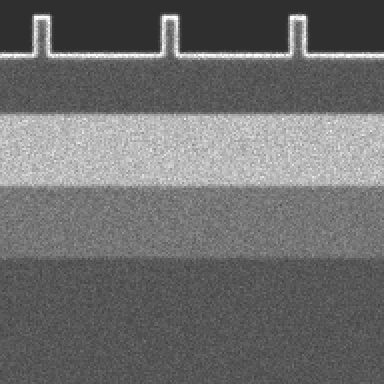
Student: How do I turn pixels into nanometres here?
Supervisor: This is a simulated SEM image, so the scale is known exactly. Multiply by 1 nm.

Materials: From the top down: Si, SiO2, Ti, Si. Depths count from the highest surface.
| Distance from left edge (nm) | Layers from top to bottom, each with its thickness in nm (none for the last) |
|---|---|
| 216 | empty 38, Si 60, SiO2 72, Ti 72, Si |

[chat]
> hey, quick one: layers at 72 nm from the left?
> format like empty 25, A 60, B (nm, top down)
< empty 38, Si 60, SiO2 72, Ti 72, Si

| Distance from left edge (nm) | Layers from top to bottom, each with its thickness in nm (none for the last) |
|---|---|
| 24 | empty 38, Si 60, SiO2 72, Ti 72, Si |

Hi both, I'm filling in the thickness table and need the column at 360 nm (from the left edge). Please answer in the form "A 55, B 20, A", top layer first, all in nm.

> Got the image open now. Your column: empty 38, Si 60, SiO2 72, Ti 72, Si